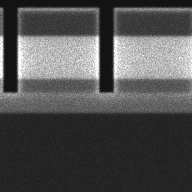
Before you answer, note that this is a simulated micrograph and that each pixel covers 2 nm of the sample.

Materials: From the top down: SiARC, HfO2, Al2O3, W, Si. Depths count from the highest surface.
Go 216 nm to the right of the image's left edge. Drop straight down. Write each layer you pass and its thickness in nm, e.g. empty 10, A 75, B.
empty 170, W 40, Si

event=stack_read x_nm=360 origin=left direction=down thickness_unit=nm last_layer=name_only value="SiARC 56, HfO2 86, Al2O3 28, W 40, Si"